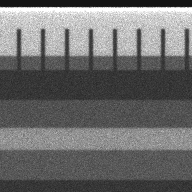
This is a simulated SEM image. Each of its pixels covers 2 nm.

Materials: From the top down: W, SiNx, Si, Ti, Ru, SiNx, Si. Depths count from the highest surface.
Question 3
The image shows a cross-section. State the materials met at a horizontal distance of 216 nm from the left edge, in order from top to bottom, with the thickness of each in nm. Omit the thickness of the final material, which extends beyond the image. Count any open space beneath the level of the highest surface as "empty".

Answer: W 96, SiNx 28, Si 60, Ti 56, Ru 44, SiNx 60, Si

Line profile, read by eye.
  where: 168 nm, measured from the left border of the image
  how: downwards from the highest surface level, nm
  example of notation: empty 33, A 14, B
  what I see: W 96, SiNx 28, Si 60, Ti 56, Ru 44, SiNx 60, Si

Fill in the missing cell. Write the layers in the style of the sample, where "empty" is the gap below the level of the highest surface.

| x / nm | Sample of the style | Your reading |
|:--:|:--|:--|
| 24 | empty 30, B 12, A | W 96, SiNx 28, Si 60, Ti 56, Ru 44, SiNx 60, Si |